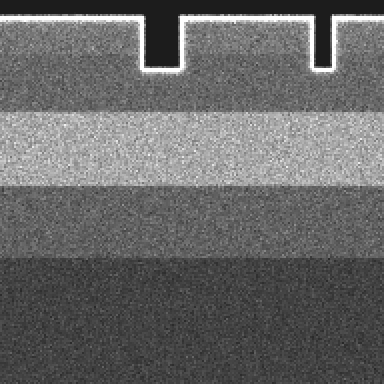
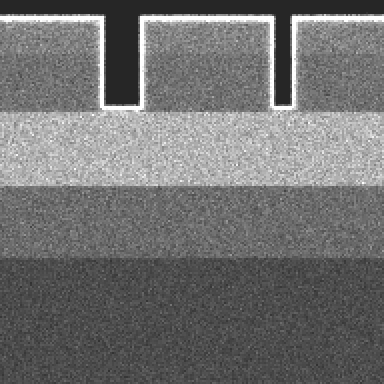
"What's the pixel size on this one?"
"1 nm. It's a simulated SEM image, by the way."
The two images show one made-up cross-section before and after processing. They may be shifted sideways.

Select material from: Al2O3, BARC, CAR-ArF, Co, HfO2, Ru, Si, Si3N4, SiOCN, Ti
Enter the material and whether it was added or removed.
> SiOCN / removed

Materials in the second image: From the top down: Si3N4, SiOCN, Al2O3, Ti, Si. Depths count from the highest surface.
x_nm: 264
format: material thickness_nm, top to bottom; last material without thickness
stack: Si3N4 38, SiOCN 58, Al2O3 74, Ti 72, Si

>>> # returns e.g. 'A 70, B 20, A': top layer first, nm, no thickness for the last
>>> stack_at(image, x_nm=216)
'Si3N4 38, SiOCN 58, Al2O3 74, Ti 72, Si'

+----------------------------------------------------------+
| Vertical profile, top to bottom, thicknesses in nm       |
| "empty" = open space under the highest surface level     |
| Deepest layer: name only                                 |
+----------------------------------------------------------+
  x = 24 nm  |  Si3N4 38, SiOCN 58, Al2O3 74, Ti 72, Si